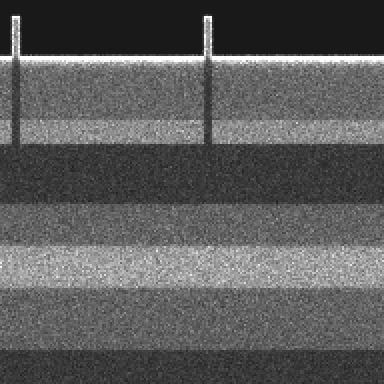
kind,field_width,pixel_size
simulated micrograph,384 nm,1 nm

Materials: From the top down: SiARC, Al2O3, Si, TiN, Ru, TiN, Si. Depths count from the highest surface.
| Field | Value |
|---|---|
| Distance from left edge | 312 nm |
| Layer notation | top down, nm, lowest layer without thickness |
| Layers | empty 40, SiARC 64, Al2O3 24, Si 60, TiN 42, Ru 42, TiN 62, Si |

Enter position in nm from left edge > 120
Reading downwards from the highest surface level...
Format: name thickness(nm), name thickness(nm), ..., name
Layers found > empty 40, SiARC 64, Al2O3 24, Si 60, TiN 42, Ru 42, TiN 62, Si